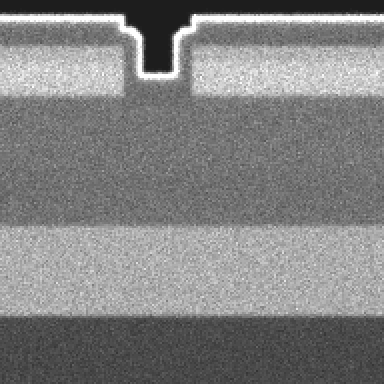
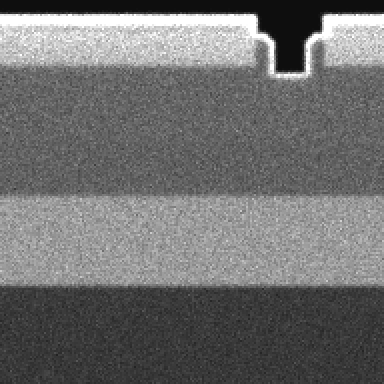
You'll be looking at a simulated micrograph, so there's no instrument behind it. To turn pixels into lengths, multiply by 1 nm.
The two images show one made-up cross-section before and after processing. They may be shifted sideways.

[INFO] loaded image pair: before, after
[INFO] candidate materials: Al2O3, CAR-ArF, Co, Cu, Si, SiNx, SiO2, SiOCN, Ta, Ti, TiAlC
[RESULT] removed SiOCN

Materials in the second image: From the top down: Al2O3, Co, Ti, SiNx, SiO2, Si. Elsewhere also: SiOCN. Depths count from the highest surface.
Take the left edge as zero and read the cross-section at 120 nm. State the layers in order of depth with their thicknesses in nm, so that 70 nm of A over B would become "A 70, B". Al2O3 16, Co 34, Ti 76, SiNx 54, SiO2 90, Si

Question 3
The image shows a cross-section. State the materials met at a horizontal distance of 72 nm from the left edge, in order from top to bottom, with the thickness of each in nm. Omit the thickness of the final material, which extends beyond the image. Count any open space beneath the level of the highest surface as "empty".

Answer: Al2O3 16, Co 34, Ti 76, SiNx 54, SiO2 90, Si